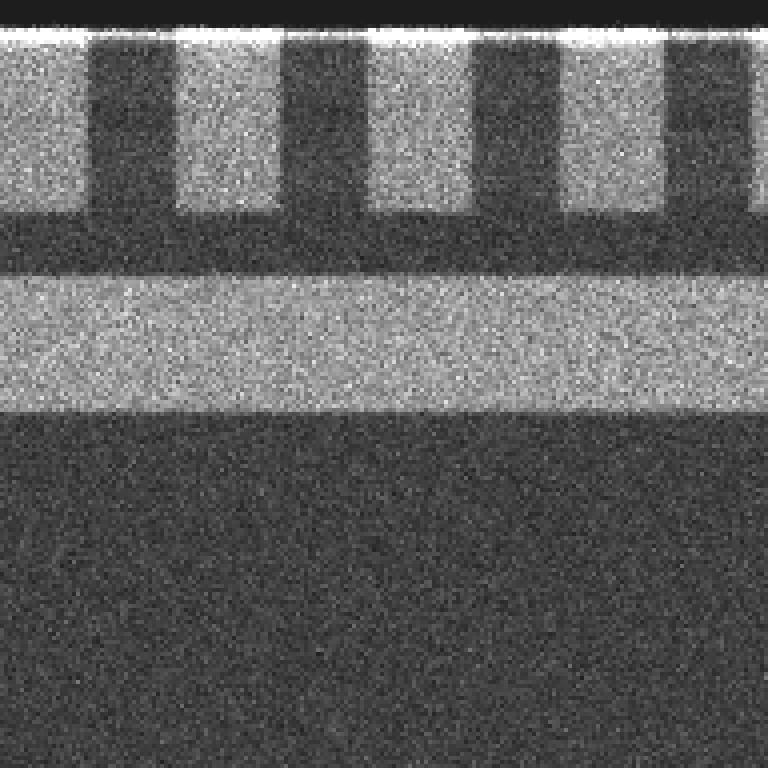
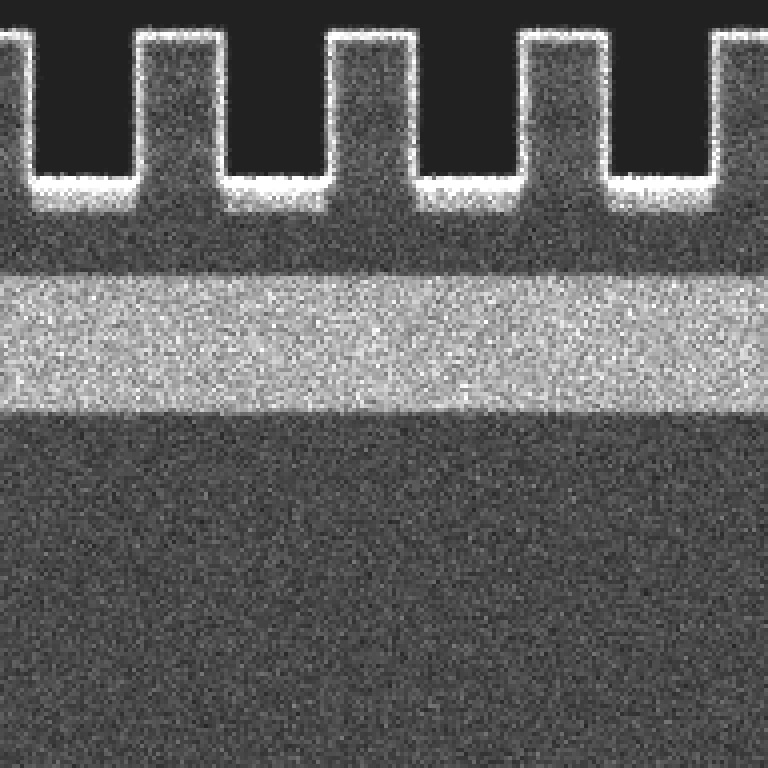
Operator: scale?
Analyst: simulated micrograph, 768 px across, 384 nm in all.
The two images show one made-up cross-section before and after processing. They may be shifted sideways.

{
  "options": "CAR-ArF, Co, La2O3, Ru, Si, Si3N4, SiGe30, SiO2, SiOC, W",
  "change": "removed",
  "material": "Co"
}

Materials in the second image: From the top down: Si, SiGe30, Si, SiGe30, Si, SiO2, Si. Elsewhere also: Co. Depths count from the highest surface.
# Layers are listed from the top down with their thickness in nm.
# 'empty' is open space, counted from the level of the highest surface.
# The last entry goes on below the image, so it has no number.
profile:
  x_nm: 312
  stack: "empty 74, Co 16, Si 32, SiO2 68, Si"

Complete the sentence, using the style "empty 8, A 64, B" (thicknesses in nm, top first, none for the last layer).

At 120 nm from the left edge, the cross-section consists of empty 74, Co 16, Si 32, SiO2 68, Si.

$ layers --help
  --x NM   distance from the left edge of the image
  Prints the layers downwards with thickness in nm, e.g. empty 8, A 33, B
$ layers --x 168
Si 14, SiGe30 22, Si 14, SiGe30 32, Si 40, SiO2 68, Si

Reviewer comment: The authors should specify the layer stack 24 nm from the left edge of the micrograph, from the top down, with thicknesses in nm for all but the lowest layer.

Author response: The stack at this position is empty 74, Co 16, Si 32, SiO2 68, Si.